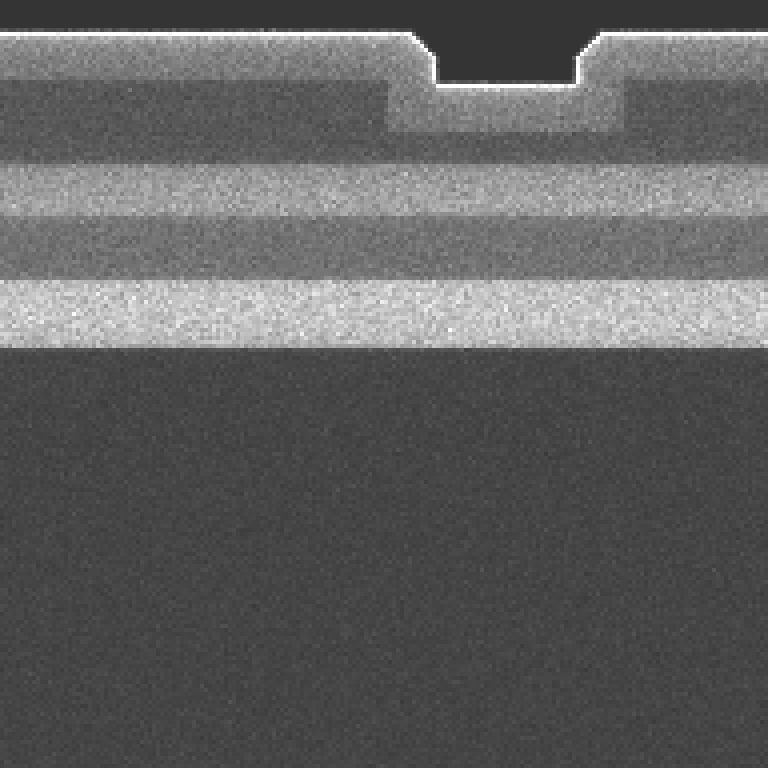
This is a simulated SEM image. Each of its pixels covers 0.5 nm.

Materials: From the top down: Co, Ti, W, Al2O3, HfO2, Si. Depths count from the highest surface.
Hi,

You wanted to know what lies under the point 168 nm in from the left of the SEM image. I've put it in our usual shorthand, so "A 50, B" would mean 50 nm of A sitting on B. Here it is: Co 24, Ti 42, W 26, Al2O3 32, HfO2 34, Si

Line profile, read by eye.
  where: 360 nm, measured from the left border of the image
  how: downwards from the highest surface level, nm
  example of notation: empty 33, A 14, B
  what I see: Co 24, Ti 42, W 26, Al2O3 32, HfO2 34, Si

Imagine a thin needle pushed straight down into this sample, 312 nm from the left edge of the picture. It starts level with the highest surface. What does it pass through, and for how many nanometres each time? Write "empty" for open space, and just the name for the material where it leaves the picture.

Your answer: Co 24, Ti 42, W 26, Al2O3 32, HfO2 34, Si